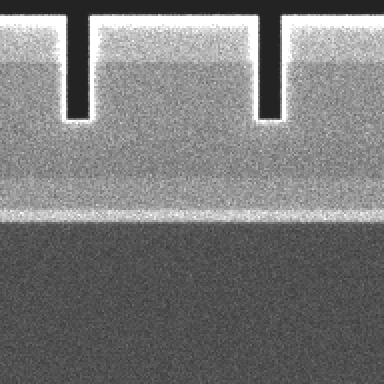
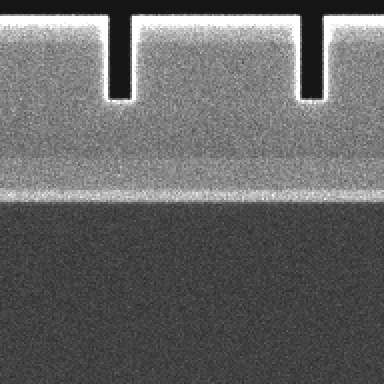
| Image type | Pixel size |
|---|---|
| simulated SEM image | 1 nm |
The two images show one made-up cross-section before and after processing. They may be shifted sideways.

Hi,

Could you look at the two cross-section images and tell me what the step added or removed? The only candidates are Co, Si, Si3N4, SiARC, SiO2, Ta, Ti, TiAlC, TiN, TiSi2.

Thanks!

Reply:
removed SiO2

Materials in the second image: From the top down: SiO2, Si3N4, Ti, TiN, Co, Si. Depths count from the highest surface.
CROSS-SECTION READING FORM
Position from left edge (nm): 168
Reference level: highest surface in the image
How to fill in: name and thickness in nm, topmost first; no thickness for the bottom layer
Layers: SiO2 26, Si3N4 58, Ti 58, TiN 32, Co 12, Si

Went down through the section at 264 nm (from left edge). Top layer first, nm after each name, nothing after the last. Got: SiO2 26, Si3N4 58, Ti 58, TiN 32, Co 12, Si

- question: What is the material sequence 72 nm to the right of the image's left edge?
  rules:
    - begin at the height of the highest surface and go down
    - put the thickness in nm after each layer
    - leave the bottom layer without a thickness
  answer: SiO2 26, Si3N4 58, Ti 58, TiN 32, Co 12, Si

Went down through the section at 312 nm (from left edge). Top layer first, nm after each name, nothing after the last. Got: empty 84, Ti 58, TiN 32, Co 12, Si